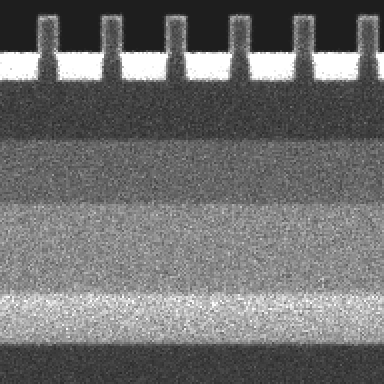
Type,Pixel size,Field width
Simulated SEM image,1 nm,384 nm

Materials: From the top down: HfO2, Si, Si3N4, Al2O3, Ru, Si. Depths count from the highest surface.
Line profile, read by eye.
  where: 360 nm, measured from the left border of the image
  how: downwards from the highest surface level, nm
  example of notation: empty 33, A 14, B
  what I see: Si 124, Si3N4 64, Al2O3 90, Ru 50, Si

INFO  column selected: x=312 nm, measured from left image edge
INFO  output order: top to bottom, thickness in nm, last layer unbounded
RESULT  Si 124, Si3N4 64, Al2O3 90, Ru 50, Si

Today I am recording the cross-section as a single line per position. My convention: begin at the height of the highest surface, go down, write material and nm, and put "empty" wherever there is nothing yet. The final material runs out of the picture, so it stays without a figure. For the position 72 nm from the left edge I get empty 38, HfO2 26, Si 60, Si3N4 64, Al2O3 90, Ru 50, Si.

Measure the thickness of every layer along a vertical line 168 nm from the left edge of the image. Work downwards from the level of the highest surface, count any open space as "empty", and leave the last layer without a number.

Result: Si 124, Si3N4 64, Al2O3 90, Ru 50, Si